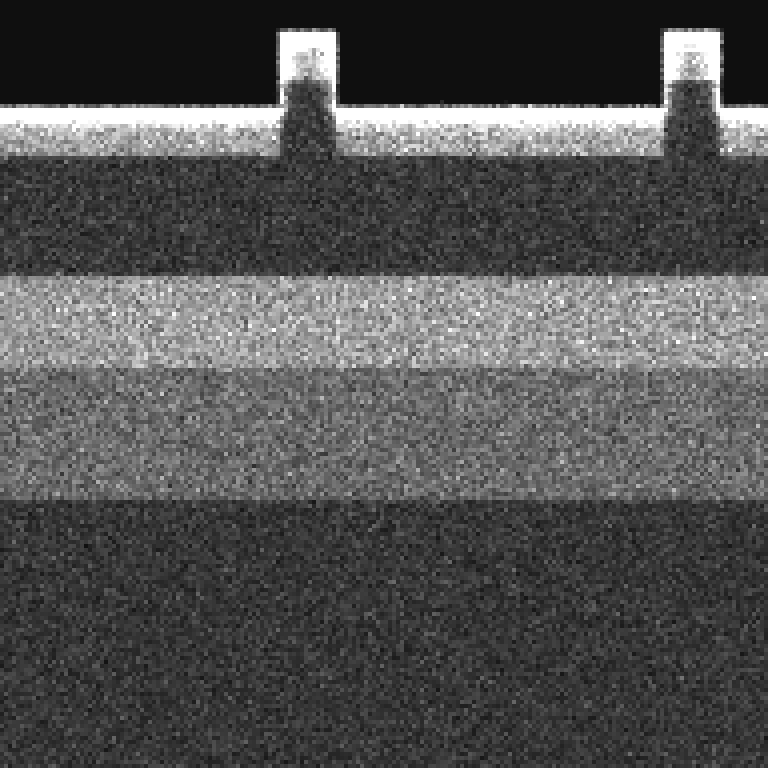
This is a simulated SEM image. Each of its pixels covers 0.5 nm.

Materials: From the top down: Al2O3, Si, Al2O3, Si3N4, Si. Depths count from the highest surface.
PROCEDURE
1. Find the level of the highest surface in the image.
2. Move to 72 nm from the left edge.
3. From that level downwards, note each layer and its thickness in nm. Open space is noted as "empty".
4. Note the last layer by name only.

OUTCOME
empty 38, Al2O3 24, Si 60, Al2O3 46, Si3N4 66, Si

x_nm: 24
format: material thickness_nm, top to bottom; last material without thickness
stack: empty 38, Al2O3 24, Si 60, Al2O3 46, Si3N4 66, Si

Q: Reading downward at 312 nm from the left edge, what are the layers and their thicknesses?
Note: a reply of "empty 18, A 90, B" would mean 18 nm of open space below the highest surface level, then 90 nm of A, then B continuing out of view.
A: empty 38, Al2O3 24, Si 60, Al2O3 46, Si3N4 66, Si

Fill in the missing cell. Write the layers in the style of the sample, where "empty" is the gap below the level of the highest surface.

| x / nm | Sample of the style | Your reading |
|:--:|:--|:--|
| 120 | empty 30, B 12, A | empty 38, Al2O3 24, Si 60, Al2O3 46, Si3N4 66, Si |